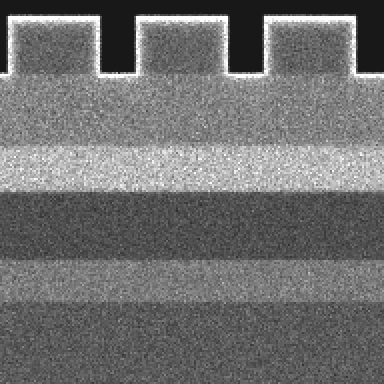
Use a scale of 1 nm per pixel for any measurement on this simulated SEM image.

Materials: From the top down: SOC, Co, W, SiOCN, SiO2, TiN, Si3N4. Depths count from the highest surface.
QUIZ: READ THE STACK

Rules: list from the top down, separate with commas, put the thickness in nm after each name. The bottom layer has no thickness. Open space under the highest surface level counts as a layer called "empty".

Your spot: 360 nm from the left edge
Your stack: empty 58, Co 72, W 46, SiOCN 68, SiO2 42, TiN 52, Si3N4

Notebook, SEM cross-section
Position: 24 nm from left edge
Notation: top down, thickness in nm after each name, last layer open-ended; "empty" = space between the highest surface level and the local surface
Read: SOC 58, Co 72, W 46, SiOCN 68, SiO2 42, TiN 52, Si3N4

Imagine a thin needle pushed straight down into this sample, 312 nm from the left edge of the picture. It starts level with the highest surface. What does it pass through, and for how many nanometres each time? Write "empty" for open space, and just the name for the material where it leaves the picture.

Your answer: SOC 58, Co 72, W 46, SiOCN 68, SiO2 42, TiN 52, Si3N4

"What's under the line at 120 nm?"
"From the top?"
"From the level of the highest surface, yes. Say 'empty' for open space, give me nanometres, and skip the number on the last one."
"empty 58, Co 72, W 46, SiOCN 68, SiO2 42, TiN 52, Si3N4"